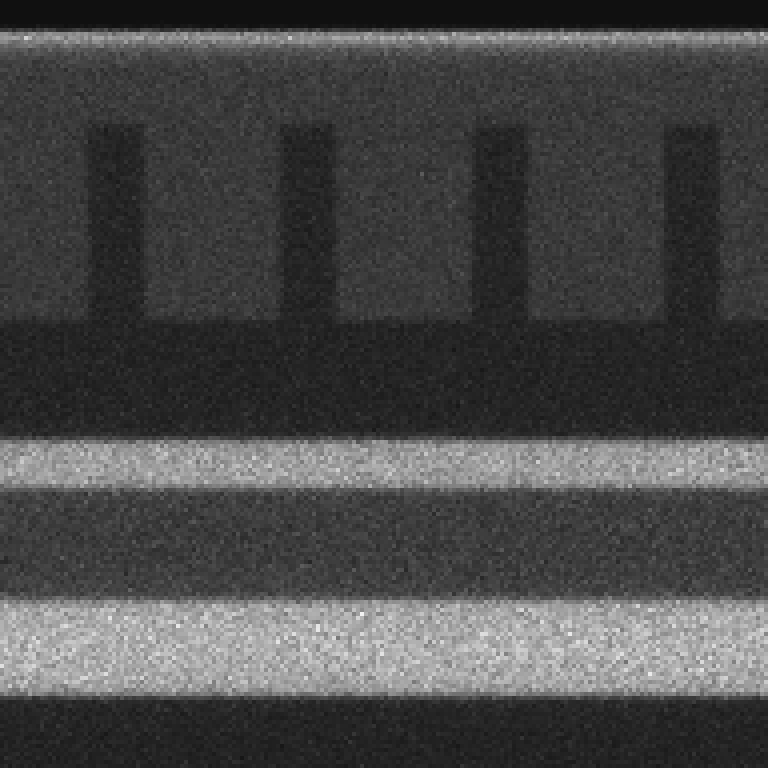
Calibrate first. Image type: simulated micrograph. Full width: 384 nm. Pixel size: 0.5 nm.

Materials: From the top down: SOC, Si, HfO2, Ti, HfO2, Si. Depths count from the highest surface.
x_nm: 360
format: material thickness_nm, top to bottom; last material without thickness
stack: SOC 144, Si 60, HfO2 24, Ti 56, HfO2 48, Si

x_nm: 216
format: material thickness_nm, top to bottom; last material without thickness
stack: SOC 144, Si 60, HfO2 24, Ti 56, HfO2 48, Si